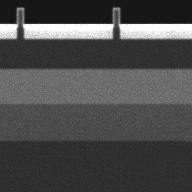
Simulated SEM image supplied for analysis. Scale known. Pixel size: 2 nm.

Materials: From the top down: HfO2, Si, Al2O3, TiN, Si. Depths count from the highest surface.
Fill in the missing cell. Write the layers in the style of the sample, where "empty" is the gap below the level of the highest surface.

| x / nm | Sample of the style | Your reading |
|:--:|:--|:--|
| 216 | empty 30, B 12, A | empty 34, HfO2 28, Si 60, Al2O3 70, TiN 74, Si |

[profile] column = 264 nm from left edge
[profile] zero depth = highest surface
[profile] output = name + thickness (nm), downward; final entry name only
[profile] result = empty 34, HfO2 28, Si 60, Al2O3 70, TiN 74, Si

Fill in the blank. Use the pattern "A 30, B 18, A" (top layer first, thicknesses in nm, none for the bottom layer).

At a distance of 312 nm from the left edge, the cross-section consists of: empty 34, HfO2 28, Si 60, Al2O3 70, TiN 74, Si